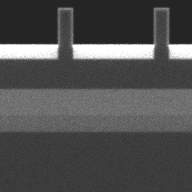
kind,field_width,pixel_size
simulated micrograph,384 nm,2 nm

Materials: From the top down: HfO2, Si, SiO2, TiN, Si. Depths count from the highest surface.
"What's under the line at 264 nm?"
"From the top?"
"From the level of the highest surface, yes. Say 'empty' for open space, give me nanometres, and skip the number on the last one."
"empty 74, HfO2 28, Si 60, SiO2 52, TiN 34, Si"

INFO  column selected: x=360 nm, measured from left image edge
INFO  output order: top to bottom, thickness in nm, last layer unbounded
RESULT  empty 74, HfO2 28, Si 60, SiO2 52, TiN 34, Si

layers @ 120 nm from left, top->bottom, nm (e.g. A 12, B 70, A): Si 162, SiO2 52, TiN 34, Si